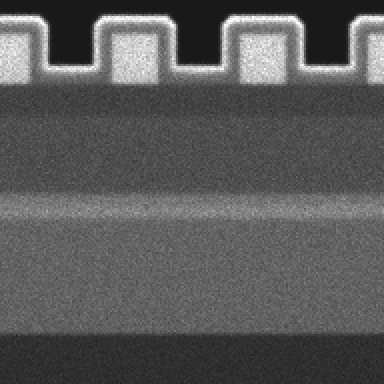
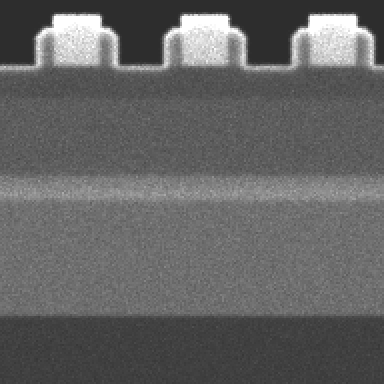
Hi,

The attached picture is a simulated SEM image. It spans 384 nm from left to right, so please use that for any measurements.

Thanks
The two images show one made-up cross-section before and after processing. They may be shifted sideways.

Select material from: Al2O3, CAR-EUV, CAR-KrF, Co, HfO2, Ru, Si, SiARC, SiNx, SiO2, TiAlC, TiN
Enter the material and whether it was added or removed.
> SiO2 / removed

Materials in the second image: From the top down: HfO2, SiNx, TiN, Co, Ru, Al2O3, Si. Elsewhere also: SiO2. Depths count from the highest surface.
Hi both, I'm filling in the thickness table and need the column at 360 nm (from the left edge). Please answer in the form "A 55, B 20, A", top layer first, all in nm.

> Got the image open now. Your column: empty 12, SiO2 38, SiNx 32, TiN 78, Co 12, Ru 12, Al2O3 116, Si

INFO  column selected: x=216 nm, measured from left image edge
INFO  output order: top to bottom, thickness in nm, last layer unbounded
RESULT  HfO2 50, SiNx 32, TiN 78, Co 12, Ru 12, Al2O3 116, Si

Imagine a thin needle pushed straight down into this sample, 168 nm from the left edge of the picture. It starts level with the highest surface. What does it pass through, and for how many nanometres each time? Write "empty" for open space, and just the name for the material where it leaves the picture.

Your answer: empty 16, SiO2 34, SiNx 32, TiN 78, Co 12, Ru 12, Al2O3 116, Si